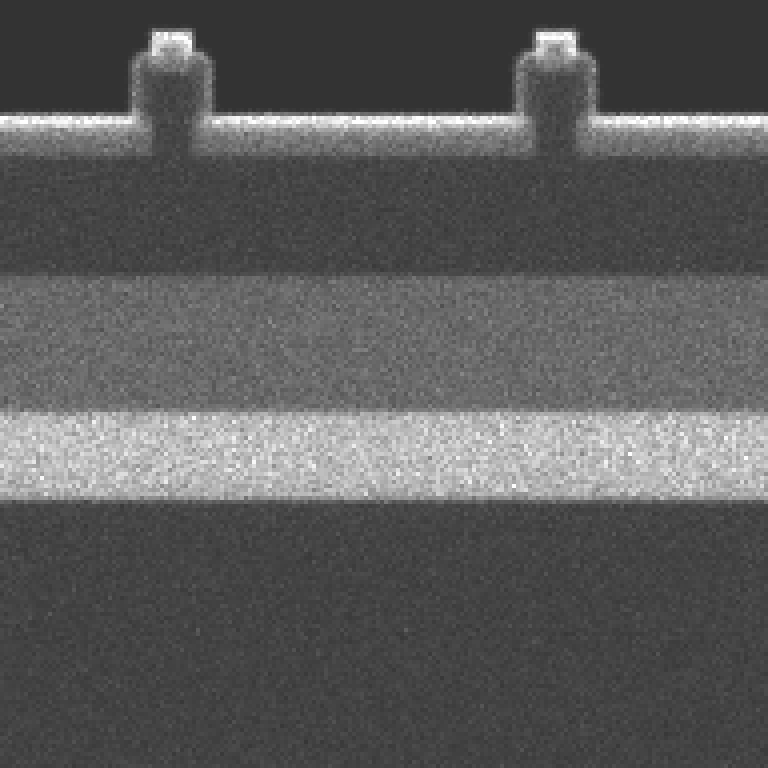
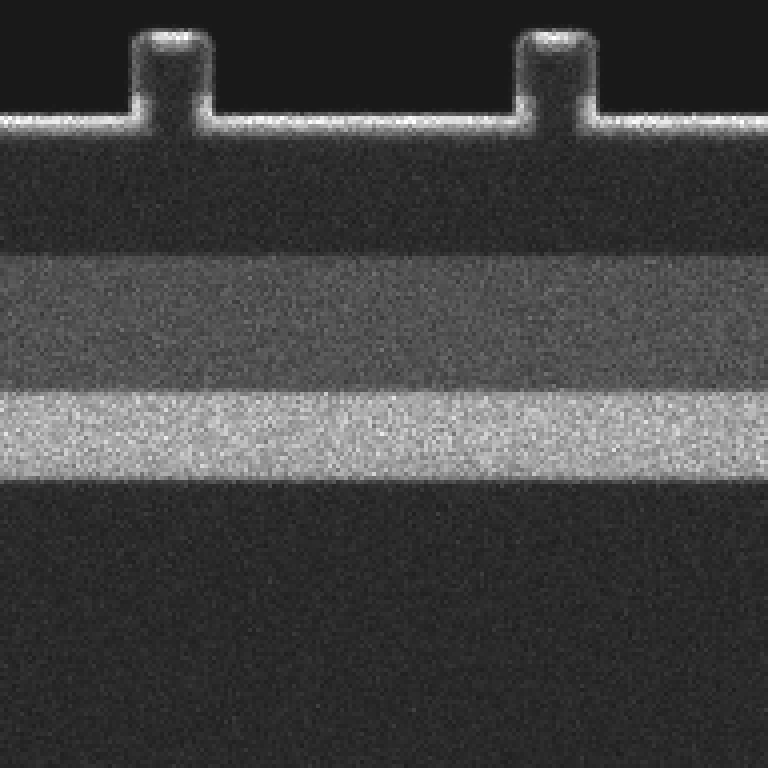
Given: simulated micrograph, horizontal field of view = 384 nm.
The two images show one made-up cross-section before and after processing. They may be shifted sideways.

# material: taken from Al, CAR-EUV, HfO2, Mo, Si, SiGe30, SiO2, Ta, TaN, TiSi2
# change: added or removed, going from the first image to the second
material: SiO2
change: removed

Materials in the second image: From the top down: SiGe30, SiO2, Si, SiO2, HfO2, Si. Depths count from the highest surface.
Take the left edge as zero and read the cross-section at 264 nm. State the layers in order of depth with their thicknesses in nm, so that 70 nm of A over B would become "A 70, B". SiGe30 32, SiO2 20, Si 60, SiO2 68, HfO2 44, Si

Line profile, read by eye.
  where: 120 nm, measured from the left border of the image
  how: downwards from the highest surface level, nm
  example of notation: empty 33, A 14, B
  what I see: empty 42, SiO2 10, Si 60, SiO2 68, HfO2 44, Si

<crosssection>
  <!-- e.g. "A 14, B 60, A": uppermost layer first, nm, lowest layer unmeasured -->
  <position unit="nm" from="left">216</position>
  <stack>empty 42, SiO2 10, Si 60, SiO2 68, HfO2 44, Si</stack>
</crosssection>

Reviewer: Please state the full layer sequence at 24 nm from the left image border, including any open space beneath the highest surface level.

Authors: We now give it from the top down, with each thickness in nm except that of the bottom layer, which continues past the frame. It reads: empty 42, SiO2 10, Si 60, SiO2 68, HfO2 44, Si